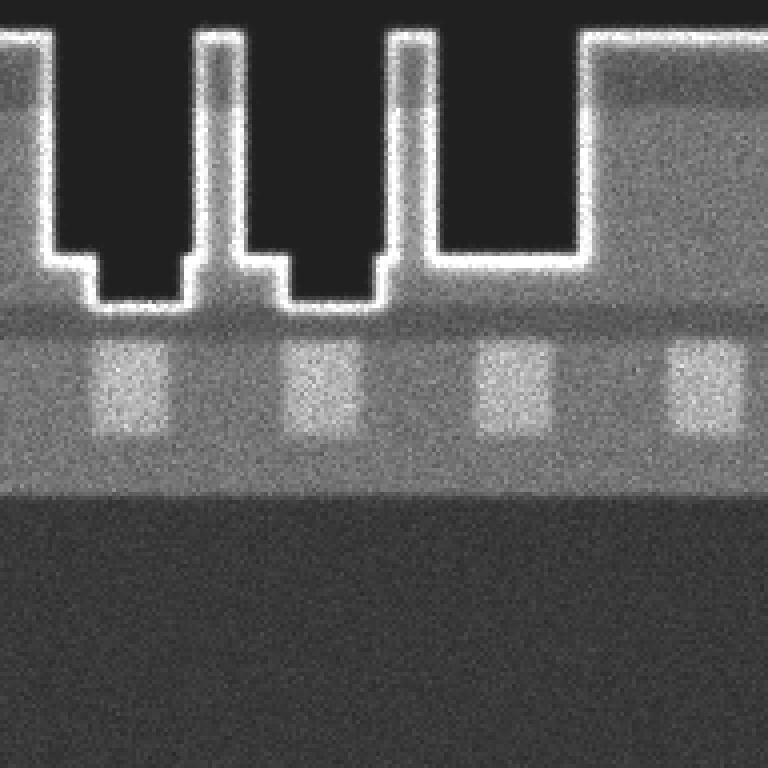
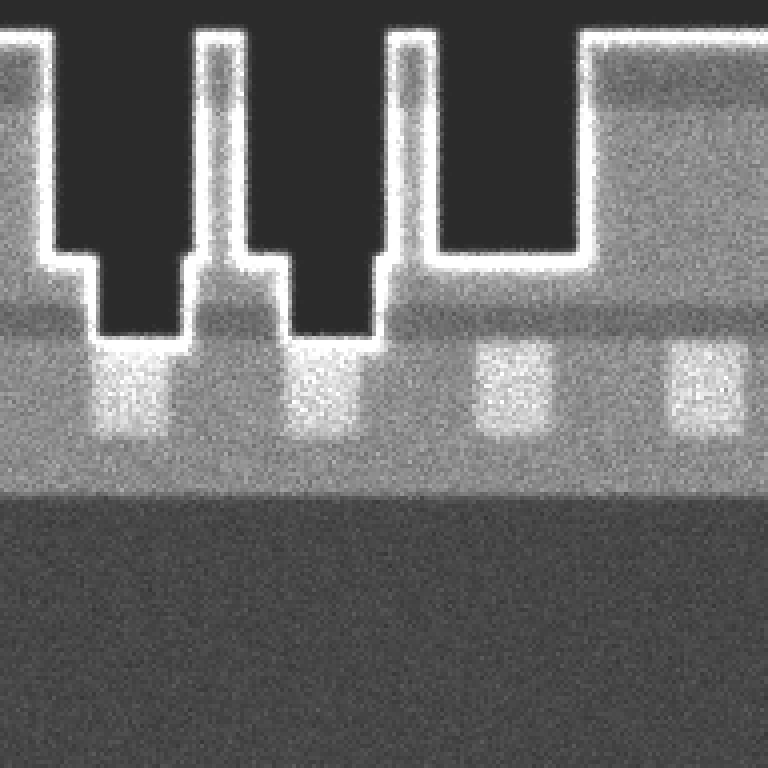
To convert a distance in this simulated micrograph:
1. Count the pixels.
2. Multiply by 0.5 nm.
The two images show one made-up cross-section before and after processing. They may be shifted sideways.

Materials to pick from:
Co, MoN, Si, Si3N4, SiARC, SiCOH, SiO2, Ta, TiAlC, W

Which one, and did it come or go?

Si3N4 - removed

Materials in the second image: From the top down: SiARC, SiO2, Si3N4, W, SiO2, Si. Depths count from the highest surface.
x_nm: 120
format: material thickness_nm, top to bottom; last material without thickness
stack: SiARC 38, SiO2 98, Si3N4 18, SiO2 78, Si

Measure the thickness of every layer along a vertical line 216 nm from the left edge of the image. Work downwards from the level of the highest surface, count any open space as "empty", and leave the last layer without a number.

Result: SiARC 38, SiO2 98, Si3N4 18, SiO2 78, Si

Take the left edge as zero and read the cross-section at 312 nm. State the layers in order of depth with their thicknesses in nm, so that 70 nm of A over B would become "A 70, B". SiARC 38, SiO2 98, Si3N4 18, SiO2 78, Si